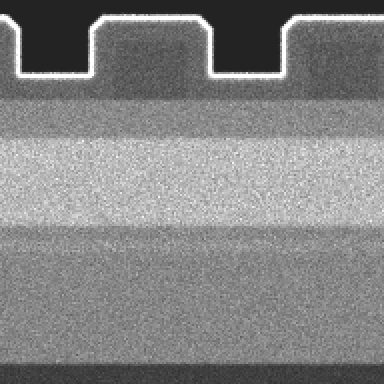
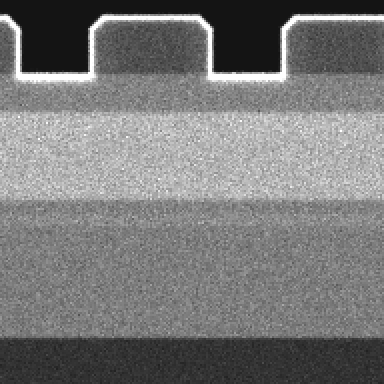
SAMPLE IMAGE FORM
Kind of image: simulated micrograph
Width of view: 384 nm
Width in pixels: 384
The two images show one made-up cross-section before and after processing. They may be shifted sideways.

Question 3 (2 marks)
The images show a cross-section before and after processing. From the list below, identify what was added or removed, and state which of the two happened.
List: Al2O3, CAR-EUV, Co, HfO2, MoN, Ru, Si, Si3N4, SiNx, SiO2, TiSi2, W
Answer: Si3N4 was removed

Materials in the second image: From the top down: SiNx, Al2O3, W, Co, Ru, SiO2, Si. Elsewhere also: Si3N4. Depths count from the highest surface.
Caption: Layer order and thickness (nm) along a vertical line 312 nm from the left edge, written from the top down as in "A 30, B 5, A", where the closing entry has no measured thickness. SiNx 58, Al2O3 38, W 88, Co 14, Ru 12, SiO2 112, Si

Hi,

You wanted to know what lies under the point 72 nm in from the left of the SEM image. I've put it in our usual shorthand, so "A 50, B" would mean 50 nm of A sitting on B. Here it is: empty 58, Al2O3 38, W 88, Co 14, Ru 12, SiO2 112, Si